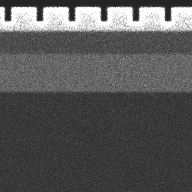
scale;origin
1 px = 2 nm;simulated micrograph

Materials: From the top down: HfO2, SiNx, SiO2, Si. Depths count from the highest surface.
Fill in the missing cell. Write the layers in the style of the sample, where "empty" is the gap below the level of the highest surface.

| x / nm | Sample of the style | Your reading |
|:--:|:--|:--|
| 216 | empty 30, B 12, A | HfO2 46, SiNx 46, SiO2 76, Si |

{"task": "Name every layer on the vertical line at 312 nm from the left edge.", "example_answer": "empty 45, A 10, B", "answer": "HfO2 46, SiNx 46, SiO2 76, Si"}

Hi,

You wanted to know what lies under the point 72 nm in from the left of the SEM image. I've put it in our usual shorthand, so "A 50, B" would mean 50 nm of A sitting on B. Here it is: empty 28, HfO2 18, SiNx 46, SiO2 76, Si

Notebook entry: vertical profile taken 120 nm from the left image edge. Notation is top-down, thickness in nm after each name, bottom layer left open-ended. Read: HfO2 46, SiNx 46, SiO2 76, Si